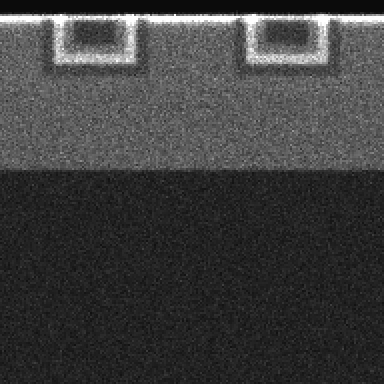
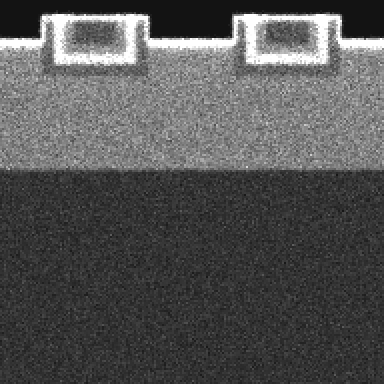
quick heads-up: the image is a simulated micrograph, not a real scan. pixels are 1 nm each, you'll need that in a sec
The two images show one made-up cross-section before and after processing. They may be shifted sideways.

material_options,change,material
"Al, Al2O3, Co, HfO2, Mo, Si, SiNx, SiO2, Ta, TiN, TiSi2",removed,Al2O3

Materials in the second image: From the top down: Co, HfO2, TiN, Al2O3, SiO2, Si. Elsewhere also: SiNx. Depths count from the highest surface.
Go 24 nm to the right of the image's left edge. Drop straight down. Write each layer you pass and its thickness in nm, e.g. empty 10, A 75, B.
empty 24, Al2O3 52, SiO2 78, Si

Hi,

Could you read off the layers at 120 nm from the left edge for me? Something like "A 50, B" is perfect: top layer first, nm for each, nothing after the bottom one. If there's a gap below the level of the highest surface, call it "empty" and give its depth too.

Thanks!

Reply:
Co 38, HfO2 10, TiN 12, Al2O3 16, SiO2 78, Si